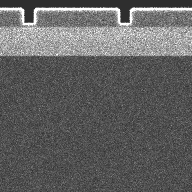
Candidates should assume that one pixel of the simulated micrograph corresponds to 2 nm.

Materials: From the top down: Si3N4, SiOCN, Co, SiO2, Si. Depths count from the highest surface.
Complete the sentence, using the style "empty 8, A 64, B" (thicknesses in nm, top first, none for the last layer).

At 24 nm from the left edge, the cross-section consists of SiOCN 38, Co 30, SiO2 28, Si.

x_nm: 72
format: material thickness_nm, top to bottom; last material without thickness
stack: Si3N4 30, SiOCN 8, Co 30, SiO2 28, Si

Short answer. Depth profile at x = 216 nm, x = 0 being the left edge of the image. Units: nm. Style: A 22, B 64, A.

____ SiOCN 38, Co 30, SiO2 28, Si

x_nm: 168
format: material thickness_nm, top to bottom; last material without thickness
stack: SiOCN 38, Co 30, SiO2 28, Si